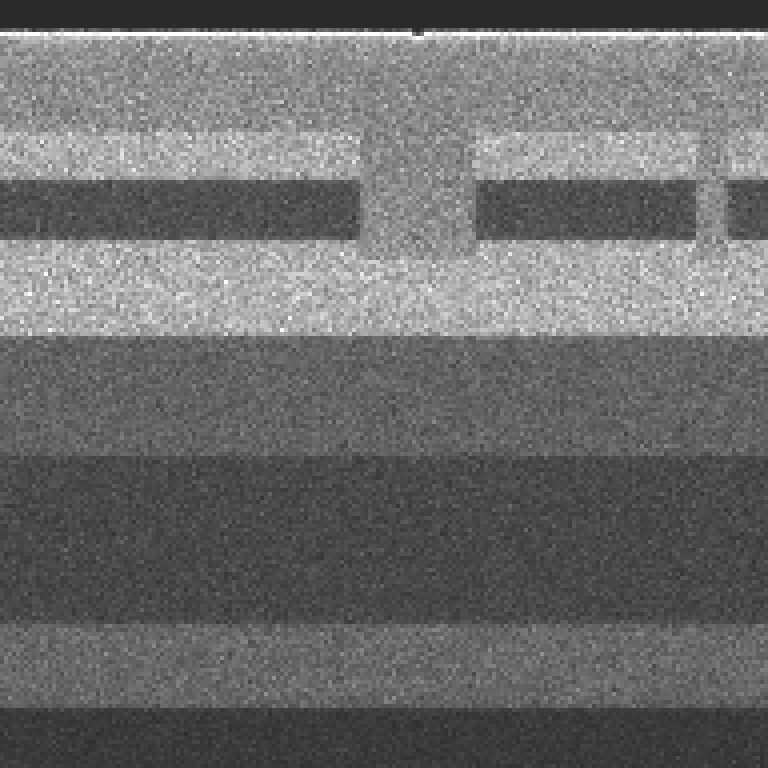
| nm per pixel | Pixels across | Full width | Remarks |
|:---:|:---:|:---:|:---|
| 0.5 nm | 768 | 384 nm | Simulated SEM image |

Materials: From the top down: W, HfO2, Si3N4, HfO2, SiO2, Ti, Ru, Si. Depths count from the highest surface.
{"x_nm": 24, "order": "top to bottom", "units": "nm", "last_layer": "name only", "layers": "W 50, HfO2 24, Si3N4 30, HfO2 48, SiO2 60, Ti 84, Ru 42, Si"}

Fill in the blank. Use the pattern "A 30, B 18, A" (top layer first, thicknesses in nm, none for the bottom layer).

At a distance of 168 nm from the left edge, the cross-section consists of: W 50, HfO2 24, Si3N4 30, HfO2 48, SiO2 60, Ti 84, Ru 42, Si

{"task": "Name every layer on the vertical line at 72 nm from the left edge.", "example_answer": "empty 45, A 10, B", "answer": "W 50, HfO2 24, Si3N4 30, HfO2 48, SiO2 60, Ti 84, Ru 42, Si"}